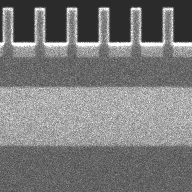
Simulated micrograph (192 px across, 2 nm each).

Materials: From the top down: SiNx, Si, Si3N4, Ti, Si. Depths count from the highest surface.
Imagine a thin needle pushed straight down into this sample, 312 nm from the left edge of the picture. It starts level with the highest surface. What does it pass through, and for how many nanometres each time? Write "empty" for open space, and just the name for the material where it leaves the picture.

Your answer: empty 70, SiNx 28, Si 60, Si3N4 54, Ti 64, Si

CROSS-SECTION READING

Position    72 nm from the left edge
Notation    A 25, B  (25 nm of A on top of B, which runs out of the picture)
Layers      Si 158, Si3N4 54, Ti 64, Si